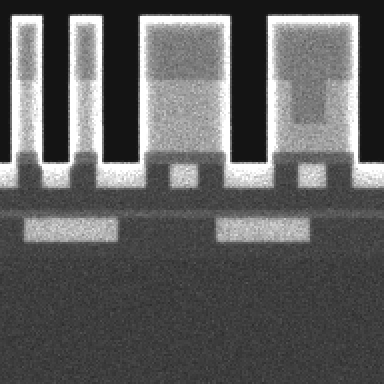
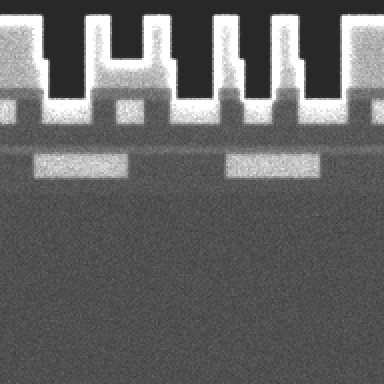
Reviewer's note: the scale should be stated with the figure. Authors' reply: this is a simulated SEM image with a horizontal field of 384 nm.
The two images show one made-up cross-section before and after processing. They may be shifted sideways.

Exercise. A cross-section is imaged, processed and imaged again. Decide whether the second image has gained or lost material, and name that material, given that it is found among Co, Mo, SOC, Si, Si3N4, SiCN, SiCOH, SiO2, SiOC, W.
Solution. removed: SOC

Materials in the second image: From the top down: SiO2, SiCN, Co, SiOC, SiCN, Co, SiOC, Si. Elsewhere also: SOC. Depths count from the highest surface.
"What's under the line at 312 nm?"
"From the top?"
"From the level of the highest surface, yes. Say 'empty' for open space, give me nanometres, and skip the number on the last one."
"empty 84, Co 24, SiOC 22, SiCN 8, Co 24, SiOC 16, Si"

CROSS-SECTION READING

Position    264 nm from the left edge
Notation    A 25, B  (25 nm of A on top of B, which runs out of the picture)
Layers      empty 84, Co 24, SiOC 22, SiCN 8, Co 24, SiOC 16, Si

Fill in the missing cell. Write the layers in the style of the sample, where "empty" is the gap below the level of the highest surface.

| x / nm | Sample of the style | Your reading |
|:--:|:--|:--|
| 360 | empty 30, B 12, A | SiO2 72, SiCN 12, SiOC 46, SiCN 8, SiOC 40, Si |